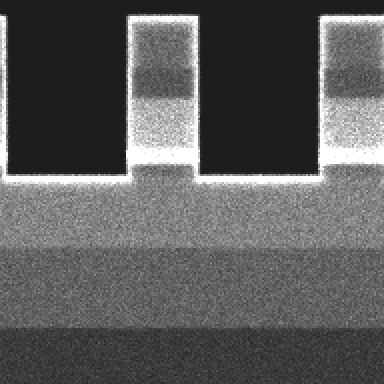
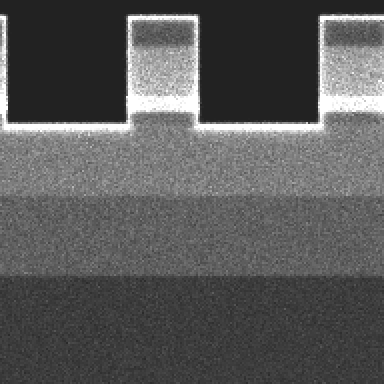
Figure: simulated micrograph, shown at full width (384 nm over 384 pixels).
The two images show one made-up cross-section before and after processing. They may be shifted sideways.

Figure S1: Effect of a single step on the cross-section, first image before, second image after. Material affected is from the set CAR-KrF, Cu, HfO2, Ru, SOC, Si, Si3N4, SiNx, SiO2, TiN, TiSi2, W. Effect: removed SOC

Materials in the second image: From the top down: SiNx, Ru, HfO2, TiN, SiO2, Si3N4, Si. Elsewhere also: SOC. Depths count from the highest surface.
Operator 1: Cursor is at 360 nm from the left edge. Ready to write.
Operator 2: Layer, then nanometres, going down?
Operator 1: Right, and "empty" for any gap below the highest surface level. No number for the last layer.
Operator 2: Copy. SiNx 30, Ru 50, HfO2 16, TiN 12, SiO2 72, Si3N4 80, Si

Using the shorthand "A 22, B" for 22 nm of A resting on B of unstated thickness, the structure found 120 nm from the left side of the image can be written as empty 108, SiO2 72, Si3N4 80, Si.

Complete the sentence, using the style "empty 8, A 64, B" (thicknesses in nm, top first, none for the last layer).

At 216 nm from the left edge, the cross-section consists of empty 108, SiO2 72, Si3N4 80, Si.